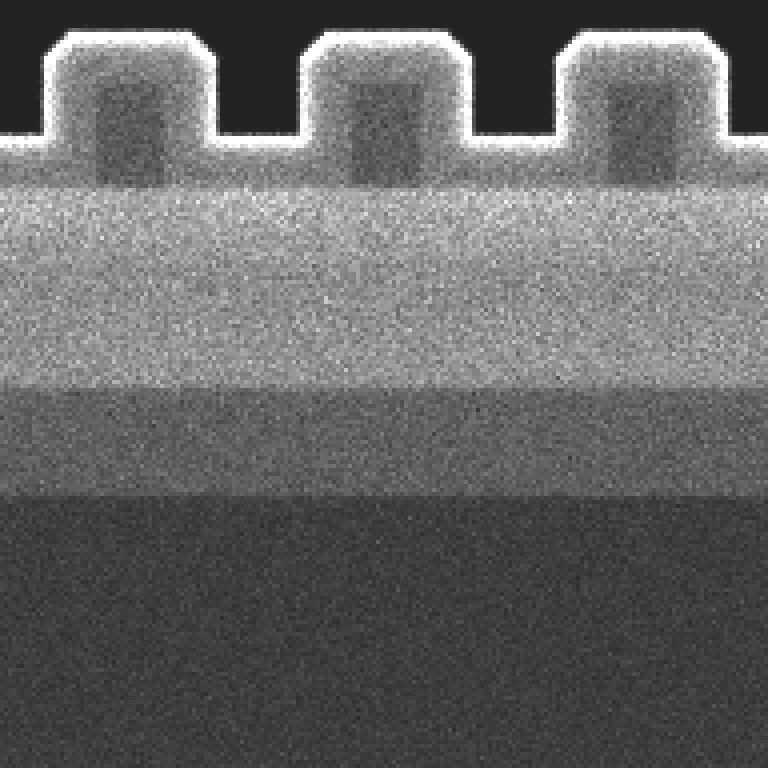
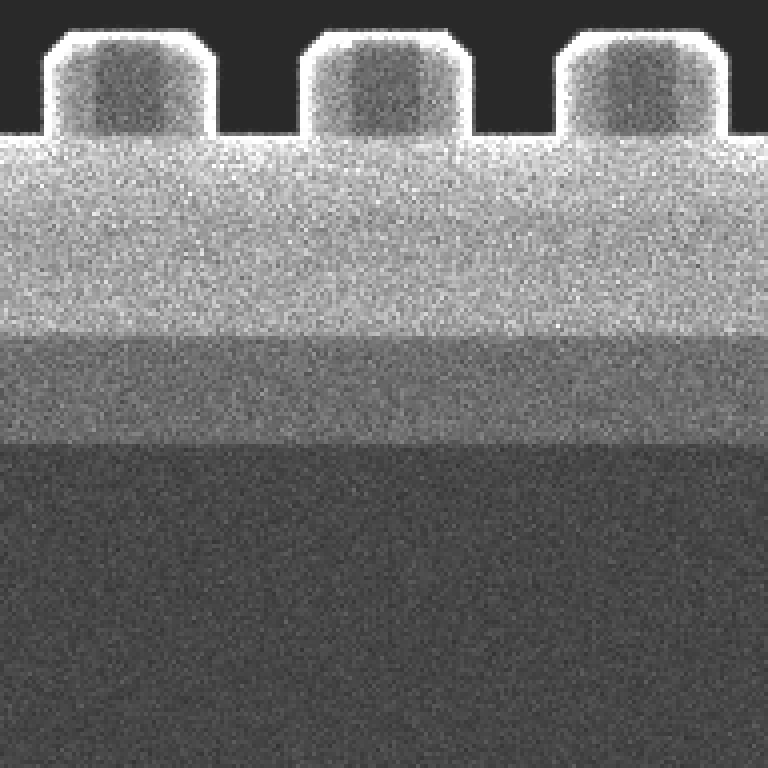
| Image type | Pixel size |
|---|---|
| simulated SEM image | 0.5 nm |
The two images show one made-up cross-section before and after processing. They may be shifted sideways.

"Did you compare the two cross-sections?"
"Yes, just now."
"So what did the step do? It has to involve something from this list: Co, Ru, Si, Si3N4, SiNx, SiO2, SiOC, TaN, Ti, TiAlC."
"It removed SiO2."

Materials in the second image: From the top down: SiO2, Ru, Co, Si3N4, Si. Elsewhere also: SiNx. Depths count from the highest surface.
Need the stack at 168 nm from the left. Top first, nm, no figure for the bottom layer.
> SiO2 52, Ru 38, Co 62, Si3N4 54, Si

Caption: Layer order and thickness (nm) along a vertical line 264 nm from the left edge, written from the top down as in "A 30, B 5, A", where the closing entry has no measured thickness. empty 52, Ru 38, Co 62, Si3N4 54, Si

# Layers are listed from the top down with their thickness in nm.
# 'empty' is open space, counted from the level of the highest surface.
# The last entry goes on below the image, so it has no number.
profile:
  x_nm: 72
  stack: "SiNx 52, Ru 38, Co 62, Si3N4 54, Si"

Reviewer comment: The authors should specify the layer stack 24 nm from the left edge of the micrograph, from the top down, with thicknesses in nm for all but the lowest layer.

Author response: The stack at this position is empty 10, SiO2 42, Ru 38, Co 62, Si3N4 54, Si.